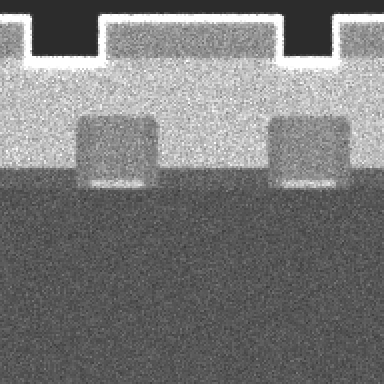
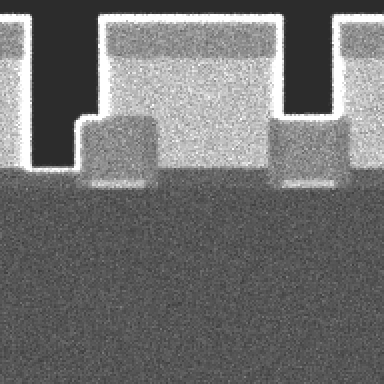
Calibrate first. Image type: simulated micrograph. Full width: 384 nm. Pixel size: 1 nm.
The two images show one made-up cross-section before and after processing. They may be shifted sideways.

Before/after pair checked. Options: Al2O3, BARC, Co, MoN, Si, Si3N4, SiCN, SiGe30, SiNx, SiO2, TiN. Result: removed SiO2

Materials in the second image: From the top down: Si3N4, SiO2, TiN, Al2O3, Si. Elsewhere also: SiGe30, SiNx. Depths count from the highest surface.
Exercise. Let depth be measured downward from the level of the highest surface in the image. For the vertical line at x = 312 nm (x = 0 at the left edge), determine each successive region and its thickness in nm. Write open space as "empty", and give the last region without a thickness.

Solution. empty 100, TiN 64, Al2O3 8, Si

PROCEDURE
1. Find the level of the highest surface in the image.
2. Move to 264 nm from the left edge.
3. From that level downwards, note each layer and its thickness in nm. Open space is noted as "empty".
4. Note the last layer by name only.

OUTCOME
Si3N4 42, SiO2 110, SiGe30 20, Si